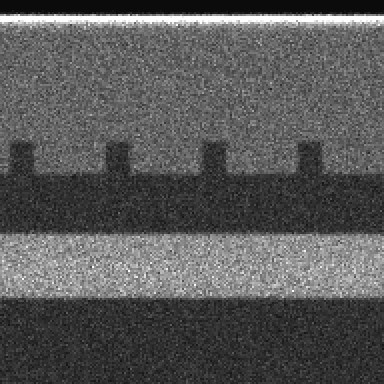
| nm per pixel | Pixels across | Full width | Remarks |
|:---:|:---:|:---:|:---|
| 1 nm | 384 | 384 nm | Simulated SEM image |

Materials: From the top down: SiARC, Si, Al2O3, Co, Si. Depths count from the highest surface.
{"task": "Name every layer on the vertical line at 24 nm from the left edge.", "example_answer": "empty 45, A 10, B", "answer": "SiARC 126, Si 92, Al2O3 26, Co 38, Si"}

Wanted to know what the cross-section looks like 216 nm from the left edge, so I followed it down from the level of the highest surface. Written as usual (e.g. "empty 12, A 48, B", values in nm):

SiARC 126, Si 92, Al2O3 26, Co 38, Si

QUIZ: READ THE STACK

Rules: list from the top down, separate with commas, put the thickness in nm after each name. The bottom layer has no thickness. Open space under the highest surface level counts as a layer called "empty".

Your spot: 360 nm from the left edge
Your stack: SiARC 158, Si 60, Al2O3 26, Co 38, Si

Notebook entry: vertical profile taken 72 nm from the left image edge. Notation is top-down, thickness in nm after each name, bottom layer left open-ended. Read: SiARC 158, Si 60, Al2O3 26, Co 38, Si